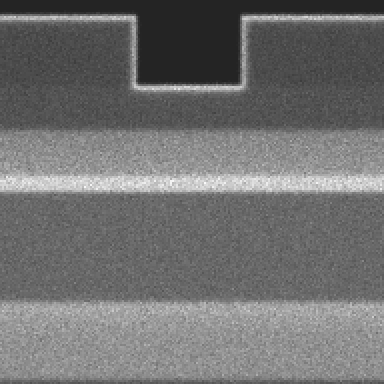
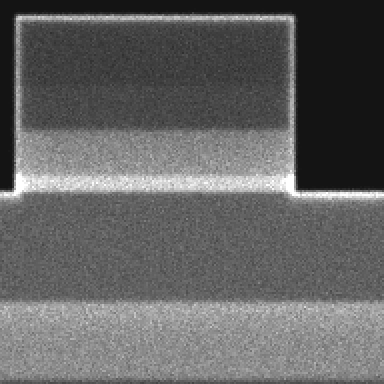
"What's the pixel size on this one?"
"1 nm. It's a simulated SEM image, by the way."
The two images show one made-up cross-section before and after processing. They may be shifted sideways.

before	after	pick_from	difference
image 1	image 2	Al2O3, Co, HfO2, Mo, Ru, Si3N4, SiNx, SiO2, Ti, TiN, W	HfO2 and Ru and Si3N4 removed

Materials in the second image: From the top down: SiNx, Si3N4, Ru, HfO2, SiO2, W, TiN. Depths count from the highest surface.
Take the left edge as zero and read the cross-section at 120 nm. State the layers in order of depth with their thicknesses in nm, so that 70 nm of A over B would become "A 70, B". SiNx 70, Si3N4 44, Ru 46, HfO2 16, SiO2 110, W 78, TiN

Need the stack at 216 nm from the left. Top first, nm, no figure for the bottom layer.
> SiNx 70, Si3N4 44, Ru 46, HfO2 16, SiO2 110, W 78, TiN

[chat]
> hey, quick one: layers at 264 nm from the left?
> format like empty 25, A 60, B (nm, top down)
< SiNx 70, Si3N4 44, Ru 46, HfO2 16, SiO2 110, W 78, TiN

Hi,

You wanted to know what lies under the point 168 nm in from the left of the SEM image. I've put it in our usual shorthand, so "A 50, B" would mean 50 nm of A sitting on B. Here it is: SiNx 70, Si3N4 44, Ru 46, HfO2 16, SiO2 110, W 78, TiN